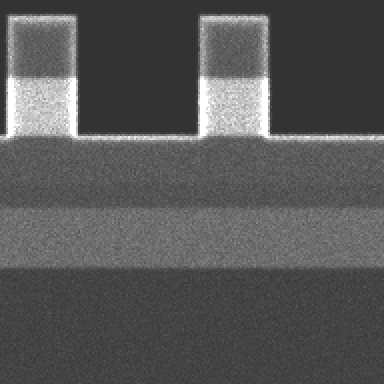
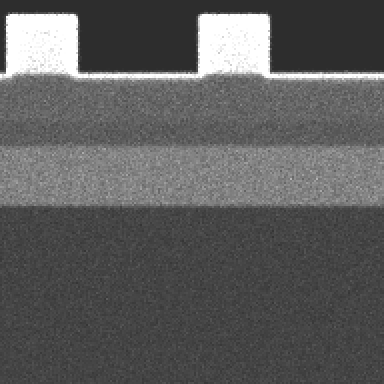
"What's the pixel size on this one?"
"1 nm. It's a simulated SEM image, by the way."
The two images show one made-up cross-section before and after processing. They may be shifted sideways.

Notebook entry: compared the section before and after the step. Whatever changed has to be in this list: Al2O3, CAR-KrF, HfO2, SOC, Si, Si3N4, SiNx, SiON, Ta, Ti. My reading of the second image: SOC removed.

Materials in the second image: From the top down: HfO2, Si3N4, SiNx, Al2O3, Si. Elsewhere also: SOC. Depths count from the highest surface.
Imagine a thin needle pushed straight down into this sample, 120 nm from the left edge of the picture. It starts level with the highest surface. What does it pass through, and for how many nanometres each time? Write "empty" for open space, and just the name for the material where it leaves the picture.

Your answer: empty 58, Si3N4 48, SiNx 24, Al2O3 60, Si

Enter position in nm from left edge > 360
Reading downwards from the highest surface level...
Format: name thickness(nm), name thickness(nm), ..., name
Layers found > empty 58, Si3N4 48, SiNx 24, Al2O3 60, Si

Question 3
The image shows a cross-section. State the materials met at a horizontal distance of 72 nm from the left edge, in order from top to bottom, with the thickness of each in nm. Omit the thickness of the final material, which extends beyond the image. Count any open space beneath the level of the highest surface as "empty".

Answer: HfO2 58, Si3N4 48, SiNx 24, Al2O3 60, Si